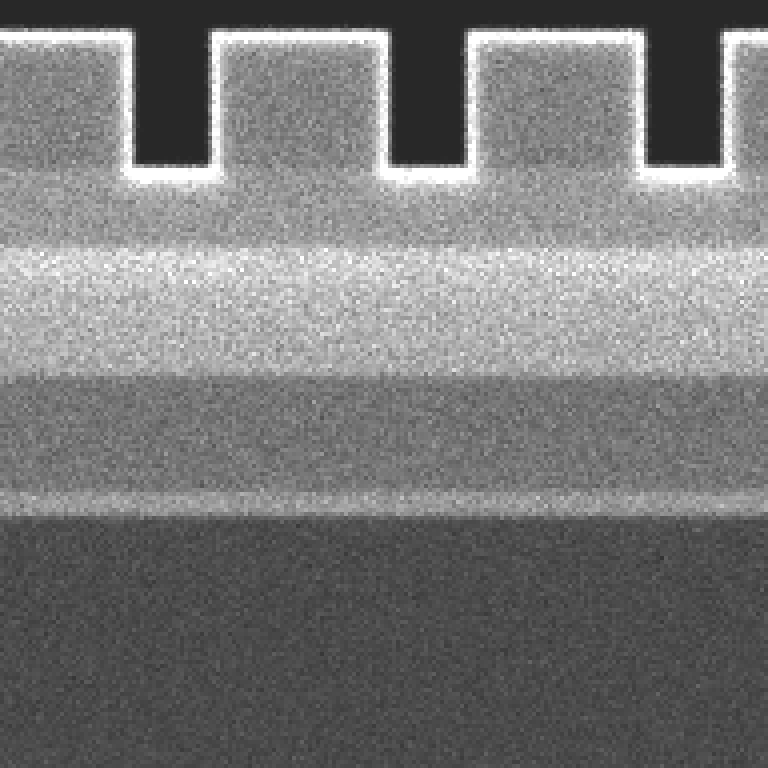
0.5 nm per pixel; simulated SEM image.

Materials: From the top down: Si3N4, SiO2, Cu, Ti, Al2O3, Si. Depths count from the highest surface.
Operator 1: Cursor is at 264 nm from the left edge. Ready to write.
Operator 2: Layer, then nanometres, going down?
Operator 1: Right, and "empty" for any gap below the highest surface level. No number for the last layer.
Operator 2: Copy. Si3N4 68, SiO2 40, Cu 64, Ti 58, Al2O3 12, Si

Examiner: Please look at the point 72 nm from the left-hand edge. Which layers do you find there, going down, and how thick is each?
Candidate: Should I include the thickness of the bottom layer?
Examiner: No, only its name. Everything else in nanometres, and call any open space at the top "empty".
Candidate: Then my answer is empty 68, SiO2 40, Cu 64, Ti 58, Al2O3 12, Si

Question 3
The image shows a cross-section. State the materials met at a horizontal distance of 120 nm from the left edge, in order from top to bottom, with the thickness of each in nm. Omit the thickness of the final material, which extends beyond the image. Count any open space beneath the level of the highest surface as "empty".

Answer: Si3N4 68, SiO2 40, Cu 64, Ti 58, Al2O3 12, Si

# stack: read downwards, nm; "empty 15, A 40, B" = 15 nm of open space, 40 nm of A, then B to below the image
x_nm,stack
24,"Si3N4 68, SiO2 40, Cu 64, Ti 58, Al2O3 12, Si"